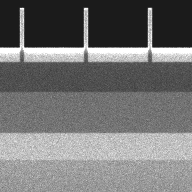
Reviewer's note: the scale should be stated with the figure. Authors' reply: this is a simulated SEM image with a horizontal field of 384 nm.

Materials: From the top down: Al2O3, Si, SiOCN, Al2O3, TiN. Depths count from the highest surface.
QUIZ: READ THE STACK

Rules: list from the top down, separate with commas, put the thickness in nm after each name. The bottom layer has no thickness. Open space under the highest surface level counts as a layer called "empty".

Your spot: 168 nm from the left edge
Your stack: Si 168, SiOCN 82, Al2O3 54, TiN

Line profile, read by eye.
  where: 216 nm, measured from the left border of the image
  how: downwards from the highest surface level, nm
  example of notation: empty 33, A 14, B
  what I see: empty 80, Al2O3 28, Si 60, SiOCN 82, Al2O3 54, TiN